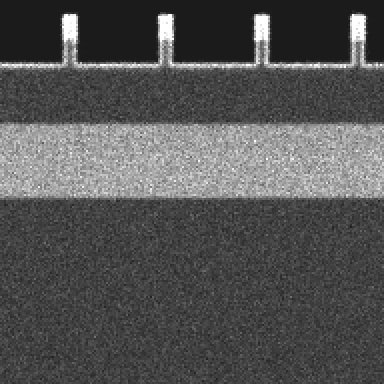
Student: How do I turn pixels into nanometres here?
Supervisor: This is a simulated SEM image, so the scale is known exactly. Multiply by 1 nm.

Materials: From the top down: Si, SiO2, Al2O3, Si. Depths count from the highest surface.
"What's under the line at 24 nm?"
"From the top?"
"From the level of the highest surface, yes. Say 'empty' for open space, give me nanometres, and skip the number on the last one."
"empty 48, Si 60, SiO2 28, Al2O3 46, Si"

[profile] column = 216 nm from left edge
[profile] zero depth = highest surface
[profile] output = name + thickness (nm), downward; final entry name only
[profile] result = empty 48, Si 60, SiO2 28, Al2O3 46, Si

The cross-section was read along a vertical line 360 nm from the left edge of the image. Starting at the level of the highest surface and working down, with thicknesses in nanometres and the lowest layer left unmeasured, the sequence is Si 108, SiO2 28, Al2O3 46, Si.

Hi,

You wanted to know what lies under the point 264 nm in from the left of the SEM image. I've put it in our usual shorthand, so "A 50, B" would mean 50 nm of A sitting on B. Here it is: Si 108, SiO2 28, Al2O3 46, Si